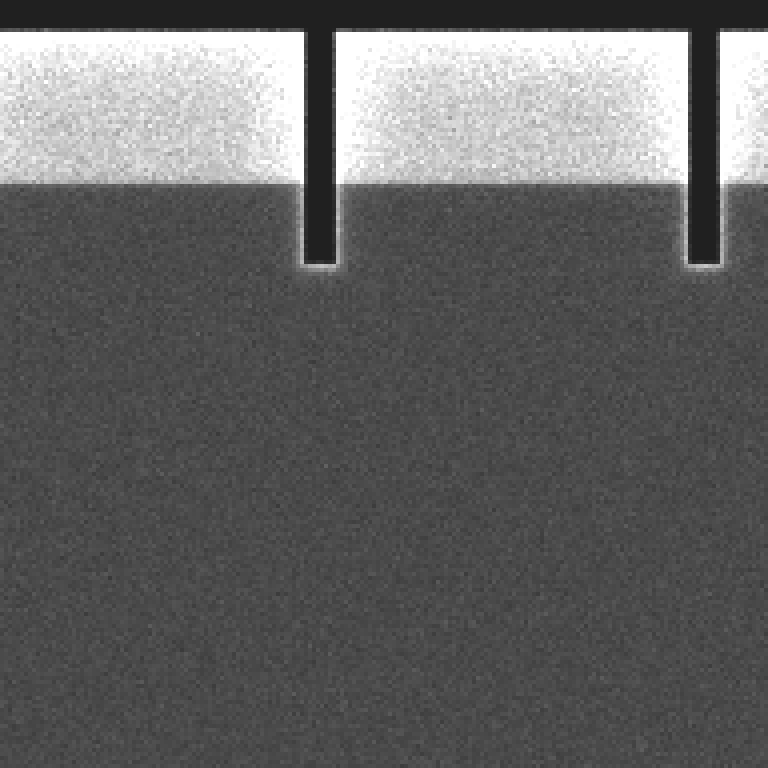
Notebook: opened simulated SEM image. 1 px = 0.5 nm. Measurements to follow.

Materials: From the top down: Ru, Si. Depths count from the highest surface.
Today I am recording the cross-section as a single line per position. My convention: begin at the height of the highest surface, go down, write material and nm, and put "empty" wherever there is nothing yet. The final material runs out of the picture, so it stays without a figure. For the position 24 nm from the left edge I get Ru 76, Si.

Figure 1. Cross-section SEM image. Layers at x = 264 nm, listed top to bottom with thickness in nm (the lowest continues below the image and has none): Ru 76, Si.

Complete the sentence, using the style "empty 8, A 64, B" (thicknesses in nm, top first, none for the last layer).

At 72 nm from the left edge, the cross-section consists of Ru 76, Si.